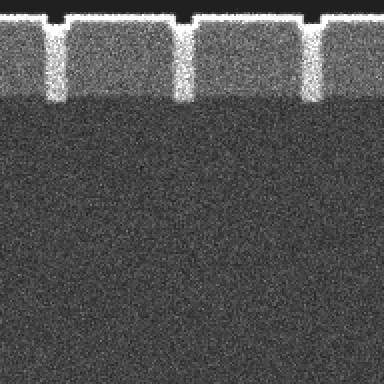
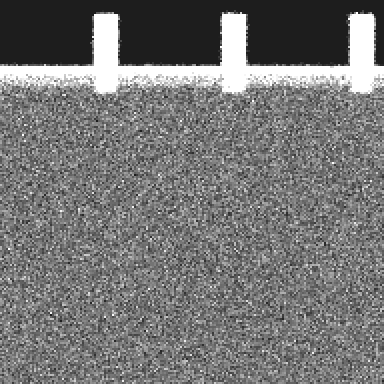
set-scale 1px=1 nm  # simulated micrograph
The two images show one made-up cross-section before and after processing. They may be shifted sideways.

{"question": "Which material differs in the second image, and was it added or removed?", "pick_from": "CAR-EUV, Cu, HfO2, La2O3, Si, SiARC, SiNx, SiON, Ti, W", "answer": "SiNx, removed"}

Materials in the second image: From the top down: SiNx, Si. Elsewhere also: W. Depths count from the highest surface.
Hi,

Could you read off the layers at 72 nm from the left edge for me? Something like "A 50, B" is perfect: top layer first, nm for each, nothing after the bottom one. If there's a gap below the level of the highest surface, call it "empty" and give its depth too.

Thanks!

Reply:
empty 52, SiNx 18, Si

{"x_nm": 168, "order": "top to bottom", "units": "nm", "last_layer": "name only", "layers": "empty 52, SiNx 18, Si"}